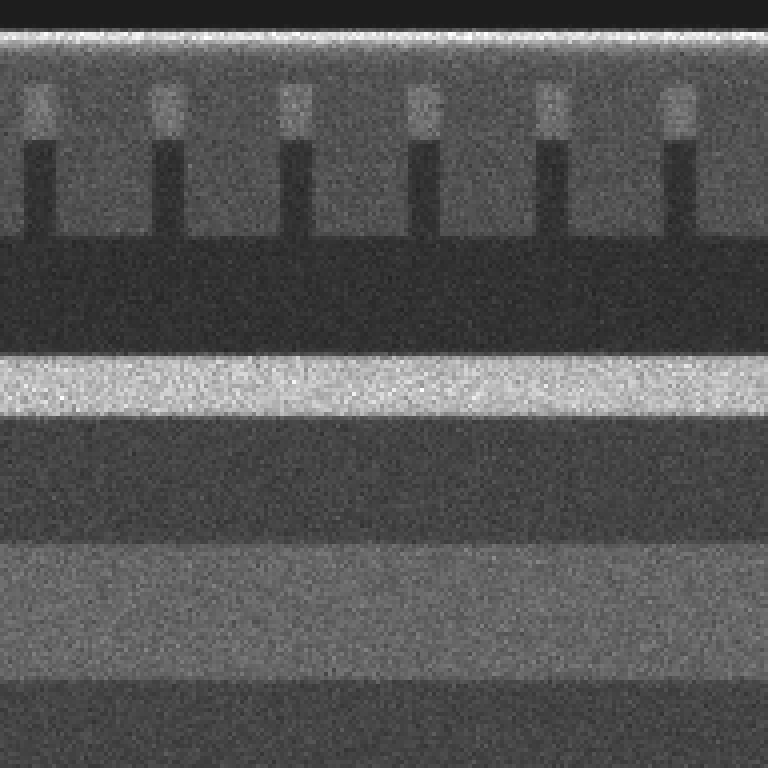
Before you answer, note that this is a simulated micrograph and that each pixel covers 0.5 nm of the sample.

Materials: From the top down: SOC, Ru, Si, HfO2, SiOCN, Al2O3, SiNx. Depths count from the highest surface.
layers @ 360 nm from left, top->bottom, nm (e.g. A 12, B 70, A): SOC 102, Si 60, HfO2 30, SiOCN 64, Al2O3 68, SiNx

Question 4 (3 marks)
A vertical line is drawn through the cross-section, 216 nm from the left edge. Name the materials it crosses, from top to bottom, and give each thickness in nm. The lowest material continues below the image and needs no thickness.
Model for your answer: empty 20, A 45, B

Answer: SOC 26, Ru 28, Si 108, HfO2 30, SiOCN 64, Al2O3 68, SiNx